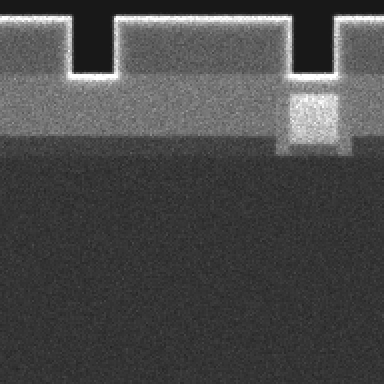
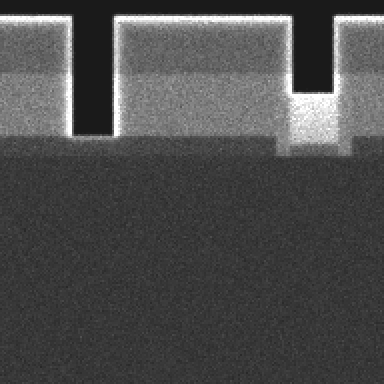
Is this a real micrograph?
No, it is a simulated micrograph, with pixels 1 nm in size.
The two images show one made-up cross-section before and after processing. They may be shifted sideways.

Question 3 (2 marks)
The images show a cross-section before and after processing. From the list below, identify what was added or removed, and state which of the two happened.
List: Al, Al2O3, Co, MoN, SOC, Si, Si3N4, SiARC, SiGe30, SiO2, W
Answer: SiO2 was removed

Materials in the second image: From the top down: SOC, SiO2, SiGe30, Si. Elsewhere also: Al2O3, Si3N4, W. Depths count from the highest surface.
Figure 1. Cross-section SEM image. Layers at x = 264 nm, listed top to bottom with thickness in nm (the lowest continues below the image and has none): SOC 58, SiO2 62, SiGe30 20, Si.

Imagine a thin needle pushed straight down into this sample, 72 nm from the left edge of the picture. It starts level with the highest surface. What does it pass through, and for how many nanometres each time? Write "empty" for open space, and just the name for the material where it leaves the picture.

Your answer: empty 120, SiGe30 20, Si